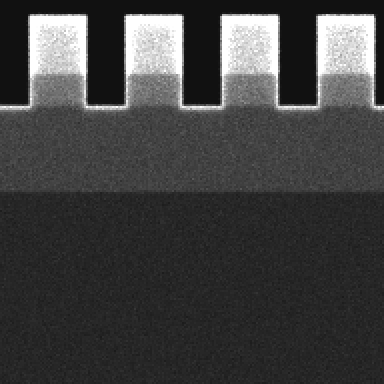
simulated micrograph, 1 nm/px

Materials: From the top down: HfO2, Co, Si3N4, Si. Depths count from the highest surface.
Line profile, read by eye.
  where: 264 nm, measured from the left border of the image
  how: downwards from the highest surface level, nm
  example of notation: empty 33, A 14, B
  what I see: HfO2 58, Co 32, Si3N4 86, Si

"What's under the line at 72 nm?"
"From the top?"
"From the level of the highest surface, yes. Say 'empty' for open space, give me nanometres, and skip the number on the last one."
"HfO2 58, Co 32, Si3N4 86, Si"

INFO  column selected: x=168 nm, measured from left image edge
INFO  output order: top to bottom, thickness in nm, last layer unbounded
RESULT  HfO2 58, Co 32, Si3N4 86, Si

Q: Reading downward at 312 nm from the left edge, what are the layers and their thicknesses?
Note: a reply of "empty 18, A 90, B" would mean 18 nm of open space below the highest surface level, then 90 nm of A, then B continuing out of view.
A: empty 90, Si3N4 86, Si